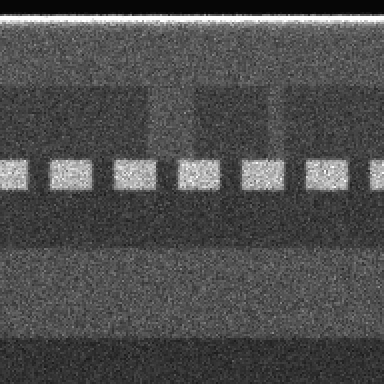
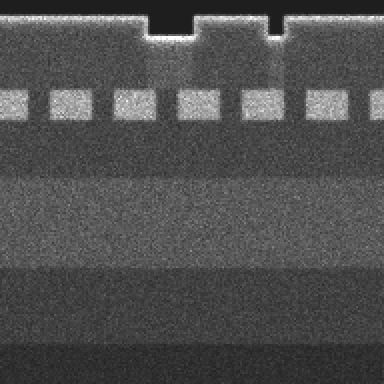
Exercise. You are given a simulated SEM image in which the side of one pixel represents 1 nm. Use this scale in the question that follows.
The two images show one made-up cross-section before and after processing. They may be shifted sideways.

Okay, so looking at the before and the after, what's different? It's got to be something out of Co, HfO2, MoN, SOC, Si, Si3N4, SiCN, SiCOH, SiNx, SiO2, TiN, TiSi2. SiO2, removed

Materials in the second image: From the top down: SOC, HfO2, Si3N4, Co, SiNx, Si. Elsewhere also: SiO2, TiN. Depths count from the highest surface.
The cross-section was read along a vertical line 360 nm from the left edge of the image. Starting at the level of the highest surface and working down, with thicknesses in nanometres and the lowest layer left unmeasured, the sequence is SOC 74, TiN 76, Si3N4 12, Co 90, SiNx 76, Si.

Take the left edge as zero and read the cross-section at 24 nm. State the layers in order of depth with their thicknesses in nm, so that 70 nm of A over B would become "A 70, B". SOC 74, HfO2 30, Si3N4 58, Co 90, SiNx 76, Si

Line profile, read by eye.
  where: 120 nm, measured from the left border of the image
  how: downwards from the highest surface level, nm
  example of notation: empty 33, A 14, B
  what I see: SOC 74, HfO2 30, Si3N4 58, Co 90, SiNx 76, Si